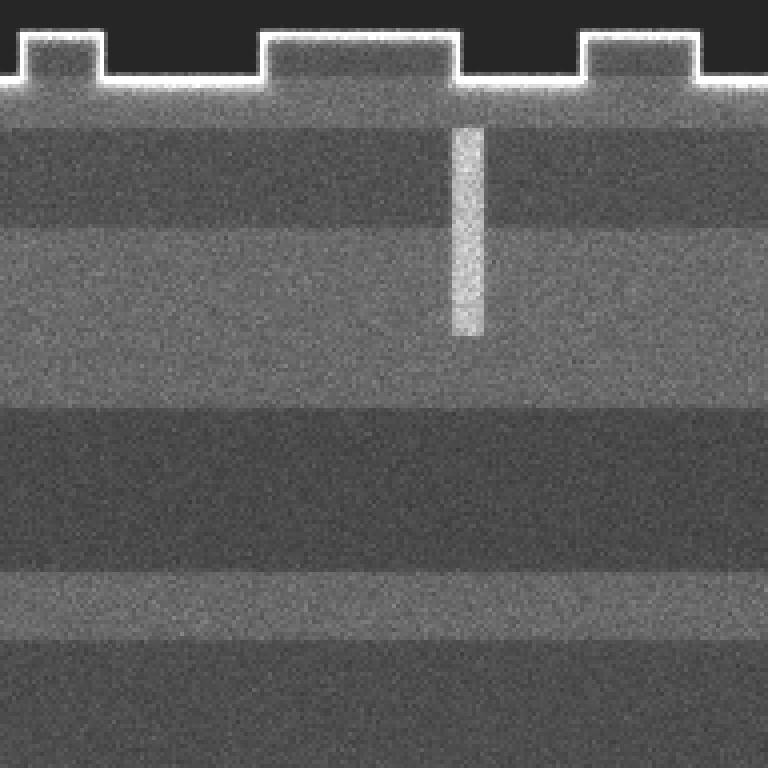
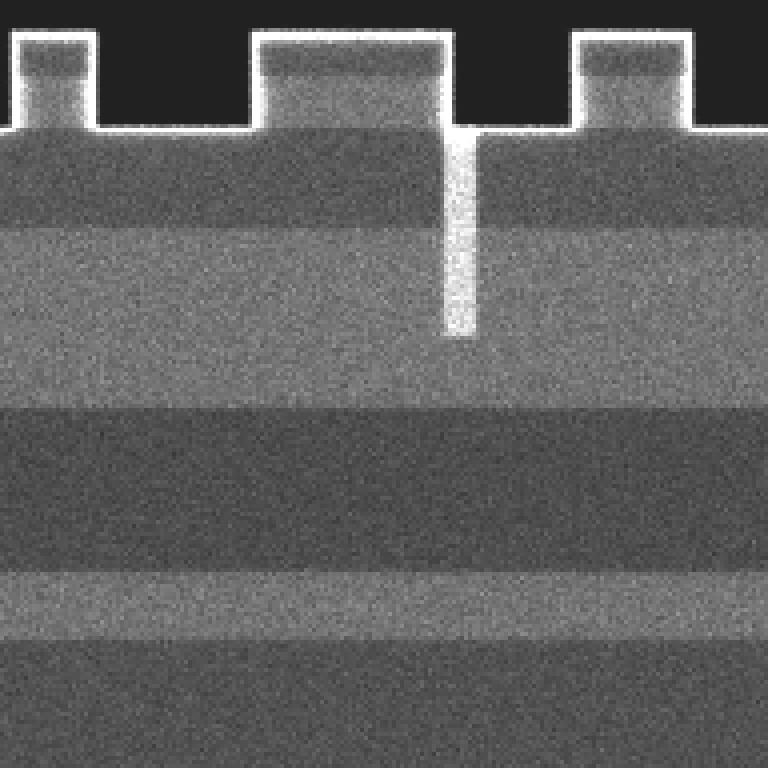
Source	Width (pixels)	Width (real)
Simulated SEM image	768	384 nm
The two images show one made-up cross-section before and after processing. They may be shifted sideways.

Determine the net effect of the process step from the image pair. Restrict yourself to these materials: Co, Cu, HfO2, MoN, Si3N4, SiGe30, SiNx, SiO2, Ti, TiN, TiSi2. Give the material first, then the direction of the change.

SiO2: removed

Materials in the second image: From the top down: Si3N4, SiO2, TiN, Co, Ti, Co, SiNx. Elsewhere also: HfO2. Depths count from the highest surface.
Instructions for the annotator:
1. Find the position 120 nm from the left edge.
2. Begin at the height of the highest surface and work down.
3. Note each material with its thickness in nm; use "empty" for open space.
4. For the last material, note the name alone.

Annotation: empty 48, TiN 50, Co 90, Ti 82, Co 34, SiNx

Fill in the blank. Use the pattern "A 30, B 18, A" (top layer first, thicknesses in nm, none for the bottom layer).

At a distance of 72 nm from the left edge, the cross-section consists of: empty 48, TiN 50, Co 90, Ti 82, Co 34, SiNx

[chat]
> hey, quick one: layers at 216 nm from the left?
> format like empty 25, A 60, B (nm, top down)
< Si3N4 22, SiO2 26, TiN 50, Co 90, Ti 82, Co 34, SiNx